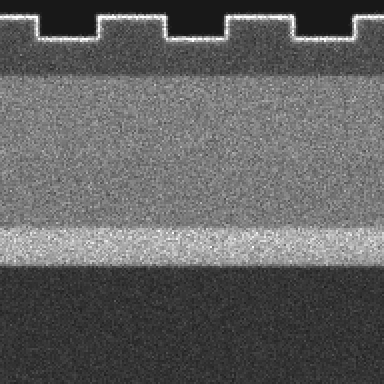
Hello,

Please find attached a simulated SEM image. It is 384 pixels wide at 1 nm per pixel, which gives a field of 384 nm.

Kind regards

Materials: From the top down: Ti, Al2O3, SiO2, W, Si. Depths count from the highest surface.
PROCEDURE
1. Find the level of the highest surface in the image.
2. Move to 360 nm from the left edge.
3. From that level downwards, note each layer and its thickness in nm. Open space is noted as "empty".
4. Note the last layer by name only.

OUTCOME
Ti 60, Al2O3 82, SiO2 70, W 38, Si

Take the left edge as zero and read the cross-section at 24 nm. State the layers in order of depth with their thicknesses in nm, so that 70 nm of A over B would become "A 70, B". Ti 60, Al2O3 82, SiO2 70, W 38, Si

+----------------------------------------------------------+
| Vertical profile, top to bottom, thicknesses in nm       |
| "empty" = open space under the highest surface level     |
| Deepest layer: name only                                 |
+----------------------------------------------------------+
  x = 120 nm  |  Ti 60, Al2O3 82, SiO2 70, W 38, Si